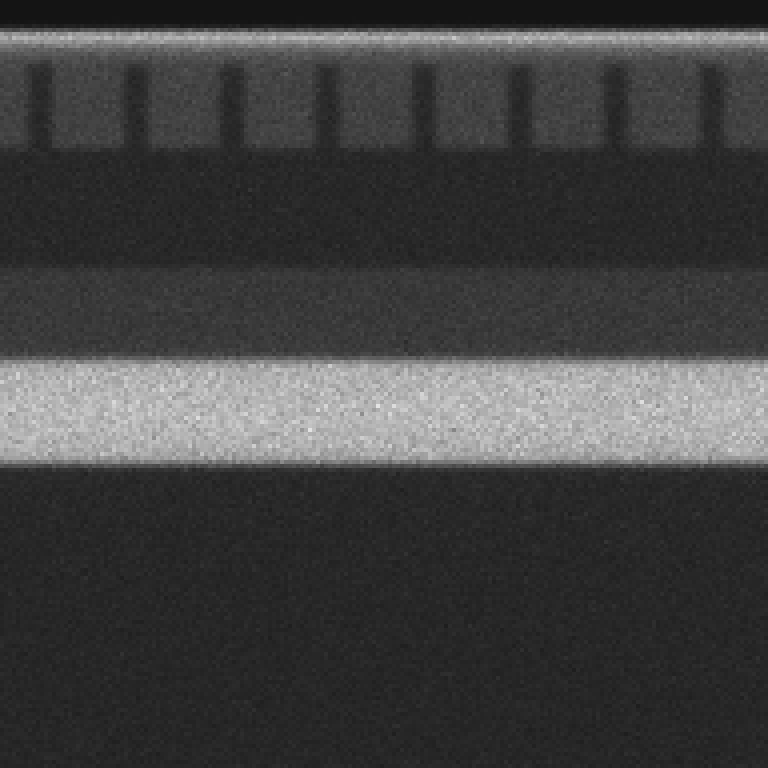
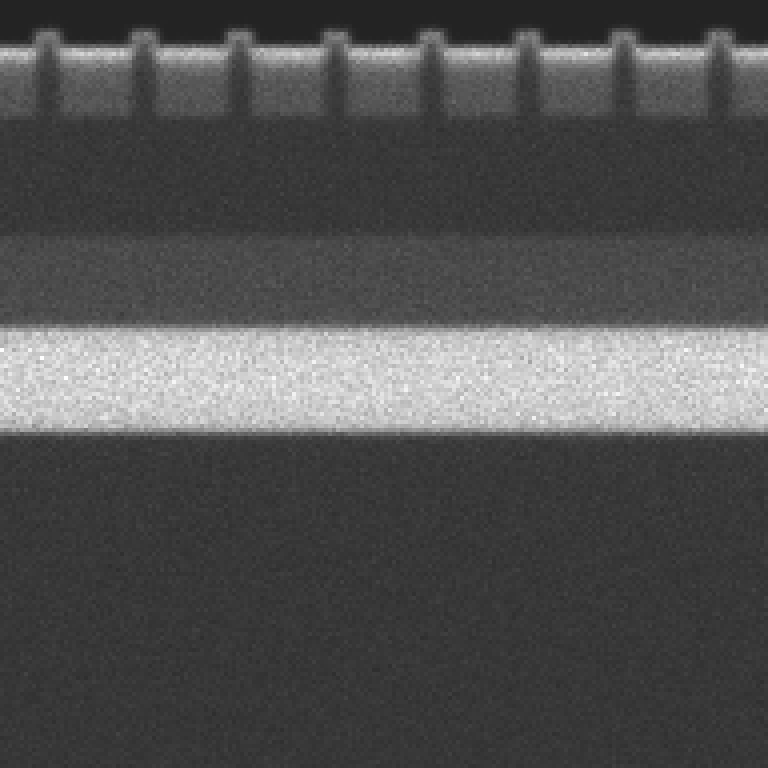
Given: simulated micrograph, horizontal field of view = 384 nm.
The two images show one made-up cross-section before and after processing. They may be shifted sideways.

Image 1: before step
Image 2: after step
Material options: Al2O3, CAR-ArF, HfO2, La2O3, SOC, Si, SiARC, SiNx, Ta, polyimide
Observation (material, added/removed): SOC, removed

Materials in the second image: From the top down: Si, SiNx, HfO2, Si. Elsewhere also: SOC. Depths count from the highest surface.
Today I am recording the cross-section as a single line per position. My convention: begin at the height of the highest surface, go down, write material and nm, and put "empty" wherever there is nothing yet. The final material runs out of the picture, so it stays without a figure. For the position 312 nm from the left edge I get Si 102, SiNx 46, HfO2 52, Si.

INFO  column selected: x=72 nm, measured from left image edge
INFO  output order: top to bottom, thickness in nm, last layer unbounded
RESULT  Si 102, SiNx 46, HfO2 52, Si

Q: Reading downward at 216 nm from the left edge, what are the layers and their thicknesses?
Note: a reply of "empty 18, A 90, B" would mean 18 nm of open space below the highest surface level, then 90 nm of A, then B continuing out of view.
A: Si 102, SiNx 46, HfO2 52, Si